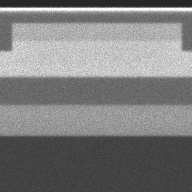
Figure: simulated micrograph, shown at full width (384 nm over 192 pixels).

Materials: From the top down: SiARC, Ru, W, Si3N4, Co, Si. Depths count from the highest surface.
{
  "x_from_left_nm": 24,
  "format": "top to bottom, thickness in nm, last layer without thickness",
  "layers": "SiARC 30, Ru 36, W 72, Si3N4 56, Co 62, Si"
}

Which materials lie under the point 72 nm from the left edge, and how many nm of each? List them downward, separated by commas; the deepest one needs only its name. SiARC 30, Ru 36, W 72, Si3N4 56, Co 62, Si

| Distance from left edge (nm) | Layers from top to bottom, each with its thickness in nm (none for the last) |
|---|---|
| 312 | SiARC 30, Ru 36, W 72, Si3N4 56, Co 62, Si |